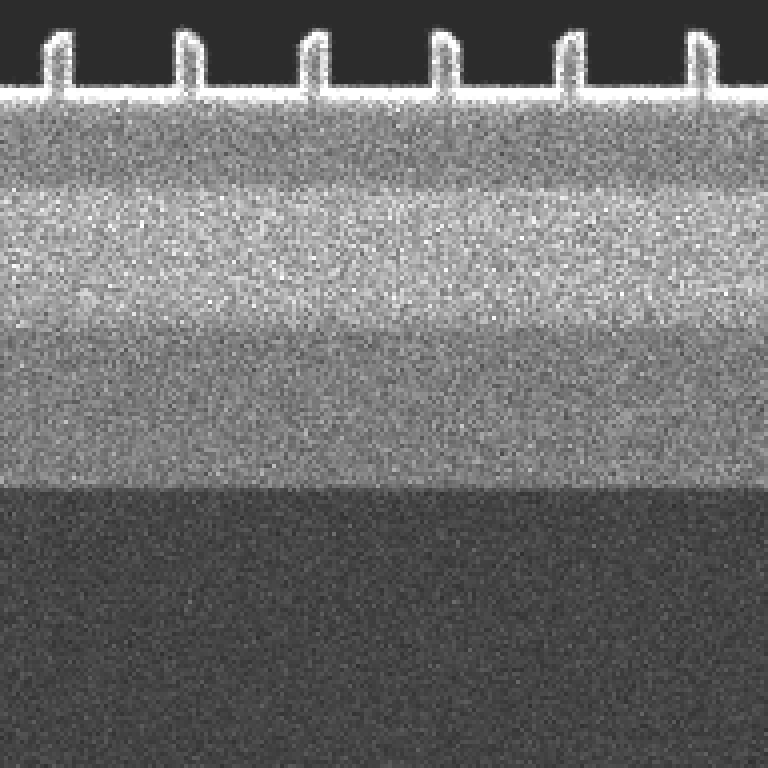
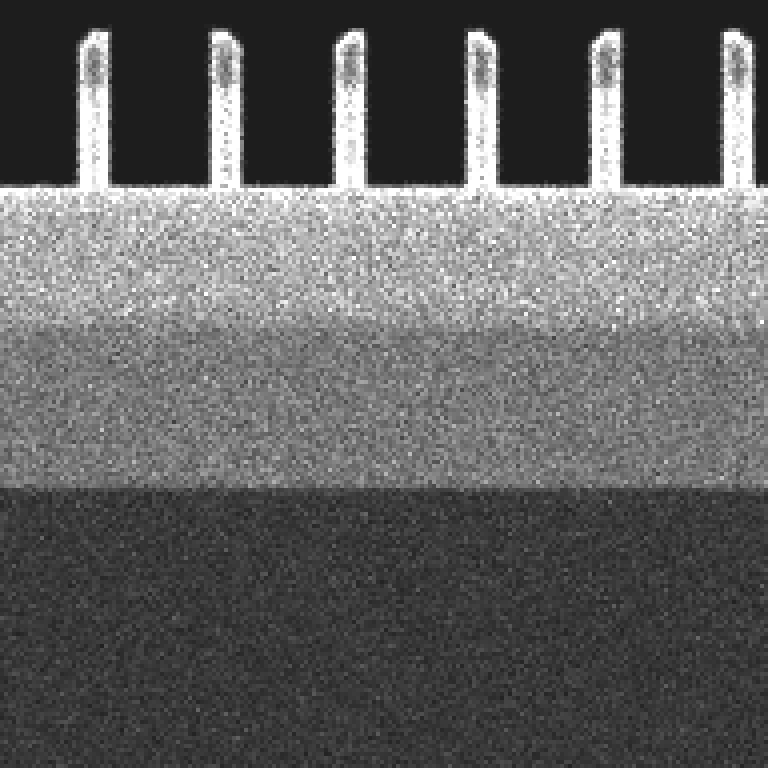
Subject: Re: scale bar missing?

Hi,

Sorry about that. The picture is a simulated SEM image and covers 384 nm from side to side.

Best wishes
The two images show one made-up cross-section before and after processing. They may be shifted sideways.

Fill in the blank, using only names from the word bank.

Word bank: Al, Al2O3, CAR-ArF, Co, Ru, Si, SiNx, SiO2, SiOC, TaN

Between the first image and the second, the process removed Al2O3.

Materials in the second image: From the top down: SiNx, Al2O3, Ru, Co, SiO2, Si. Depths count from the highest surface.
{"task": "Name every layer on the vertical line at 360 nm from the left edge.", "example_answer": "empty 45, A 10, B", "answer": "empty 78, Ru 60, Co 10, SiO2 80, Si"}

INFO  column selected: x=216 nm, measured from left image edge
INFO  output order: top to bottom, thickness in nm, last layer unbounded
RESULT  empty 78, Ru 60, Co 10, SiO2 80, Si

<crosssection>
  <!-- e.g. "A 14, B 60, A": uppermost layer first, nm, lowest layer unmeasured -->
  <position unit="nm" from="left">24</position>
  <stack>empty 78, Ru 60, Co 10, SiO2 80, Si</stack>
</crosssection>